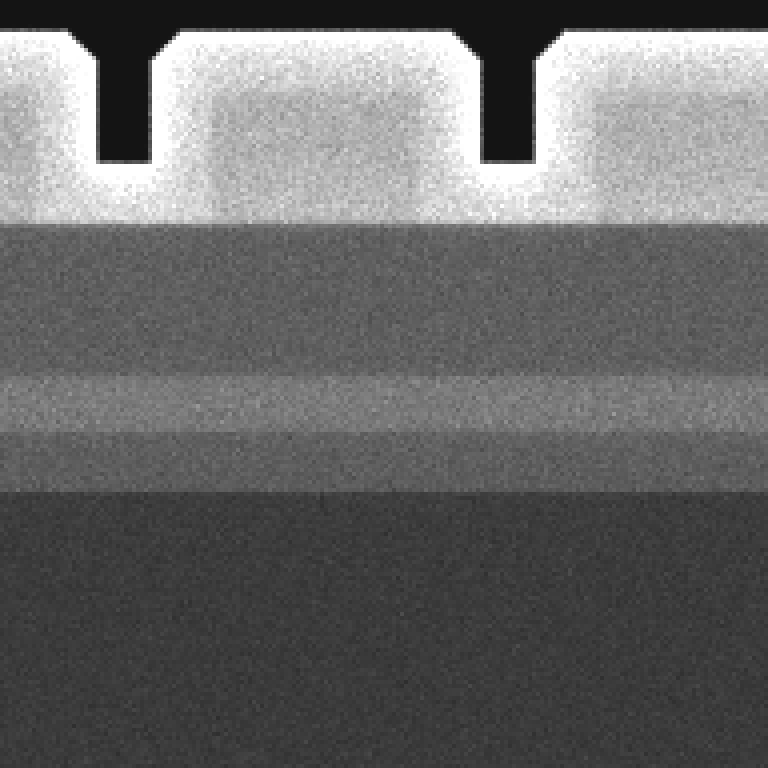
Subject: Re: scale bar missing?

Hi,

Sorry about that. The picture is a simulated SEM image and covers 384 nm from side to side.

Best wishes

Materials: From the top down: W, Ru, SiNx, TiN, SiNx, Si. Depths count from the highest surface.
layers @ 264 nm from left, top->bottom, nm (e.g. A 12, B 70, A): empty 66, W 30, SiNx 76, TiN 28, SiNx 30, Si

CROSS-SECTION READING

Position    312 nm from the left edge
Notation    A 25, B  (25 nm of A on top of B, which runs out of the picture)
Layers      W 30, Ru 66, SiNx 76, TiN 28, SiNx 30, Si